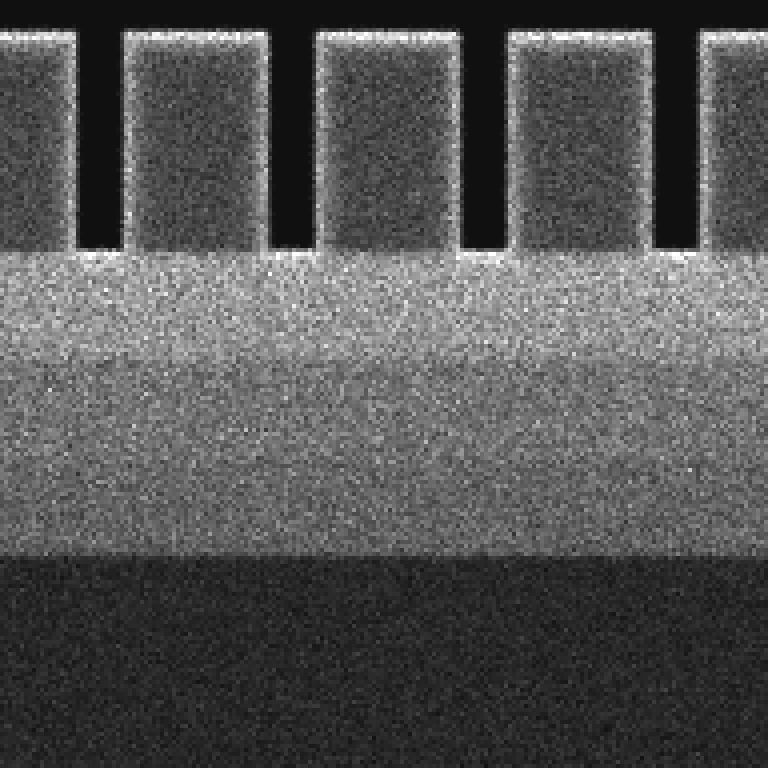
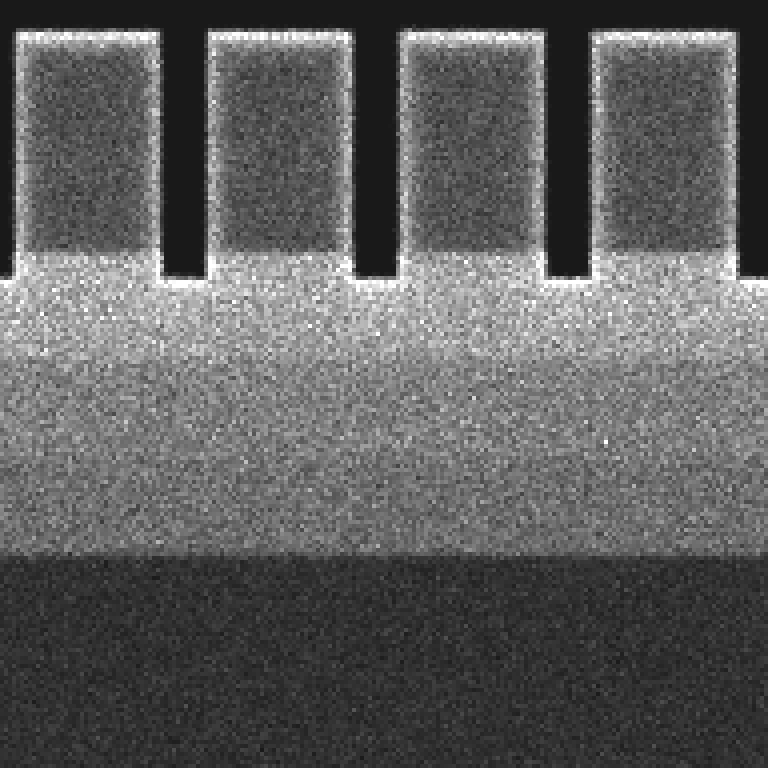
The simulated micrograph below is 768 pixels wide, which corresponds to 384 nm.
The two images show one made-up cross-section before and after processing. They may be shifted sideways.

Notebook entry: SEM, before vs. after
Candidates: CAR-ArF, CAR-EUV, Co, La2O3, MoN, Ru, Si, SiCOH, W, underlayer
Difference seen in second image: W removed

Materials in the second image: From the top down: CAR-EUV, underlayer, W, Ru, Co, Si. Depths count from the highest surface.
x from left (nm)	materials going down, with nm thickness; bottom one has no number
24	CAR-EUV 56, underlayer 54, W 54, Ru 50, Co 48, Si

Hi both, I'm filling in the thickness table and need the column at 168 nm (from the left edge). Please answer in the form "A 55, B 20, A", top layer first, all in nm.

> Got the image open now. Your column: CAR-EUV 56, underlayer 54, W 54, Ru 50, Co 48, Si